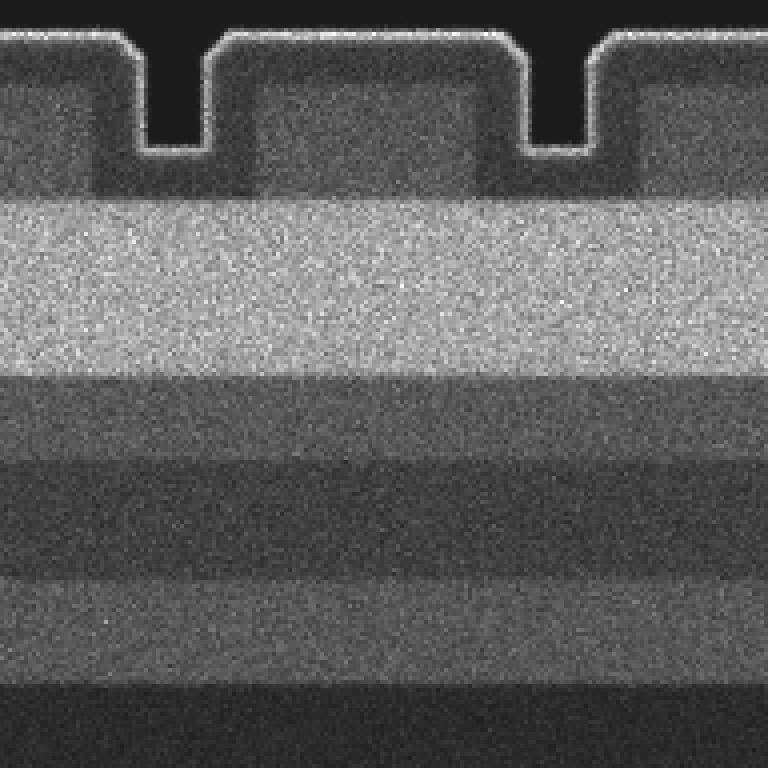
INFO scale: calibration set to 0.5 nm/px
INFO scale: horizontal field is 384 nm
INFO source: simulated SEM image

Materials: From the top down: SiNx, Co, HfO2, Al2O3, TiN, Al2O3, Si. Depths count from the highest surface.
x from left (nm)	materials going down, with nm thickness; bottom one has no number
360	SiNx 26, Co 58, HfO2 88, Al2O3 42, TiN 60, Al2O3 52, Si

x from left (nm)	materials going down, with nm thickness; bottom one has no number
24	SiNx 26, Co 58, HfO2 88, Al2O3 42, TiN 60, Al2O3 52, Si